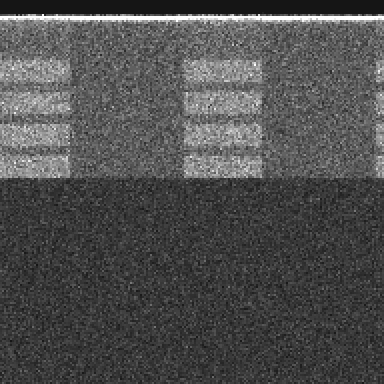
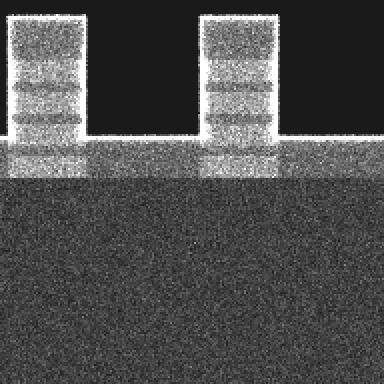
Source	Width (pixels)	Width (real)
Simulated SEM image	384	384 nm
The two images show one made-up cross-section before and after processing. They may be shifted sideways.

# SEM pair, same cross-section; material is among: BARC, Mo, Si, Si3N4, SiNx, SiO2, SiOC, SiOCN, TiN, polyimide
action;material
removed;SiNx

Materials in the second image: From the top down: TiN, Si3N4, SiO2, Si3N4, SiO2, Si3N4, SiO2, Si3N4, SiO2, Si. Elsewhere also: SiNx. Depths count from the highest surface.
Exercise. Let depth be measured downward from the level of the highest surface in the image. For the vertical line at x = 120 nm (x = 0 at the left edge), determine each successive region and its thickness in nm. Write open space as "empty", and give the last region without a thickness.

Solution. empty 120, SiNx 42, Si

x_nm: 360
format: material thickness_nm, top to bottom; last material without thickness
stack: empty 120, SiNx 42, Si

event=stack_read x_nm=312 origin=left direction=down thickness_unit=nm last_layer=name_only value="empty 120, SiNx 42, Si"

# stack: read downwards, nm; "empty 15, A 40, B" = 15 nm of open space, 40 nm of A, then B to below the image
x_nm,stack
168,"empty 120, SiNx 42, Si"